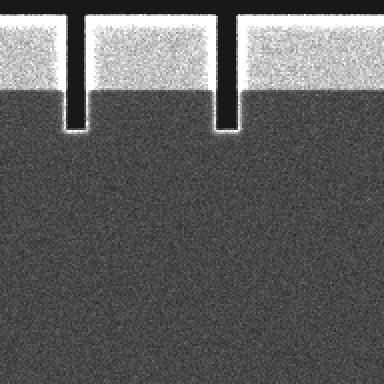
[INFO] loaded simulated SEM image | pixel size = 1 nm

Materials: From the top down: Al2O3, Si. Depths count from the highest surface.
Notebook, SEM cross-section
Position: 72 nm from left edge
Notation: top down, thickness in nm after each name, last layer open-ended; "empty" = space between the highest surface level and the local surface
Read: empty 114, Si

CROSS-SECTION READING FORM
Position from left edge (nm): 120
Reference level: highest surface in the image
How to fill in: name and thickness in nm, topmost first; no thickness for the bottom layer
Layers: Al2O3 74, Si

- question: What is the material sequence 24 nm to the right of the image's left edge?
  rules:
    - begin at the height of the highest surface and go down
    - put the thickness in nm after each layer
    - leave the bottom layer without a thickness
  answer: Al2O3 74, Si